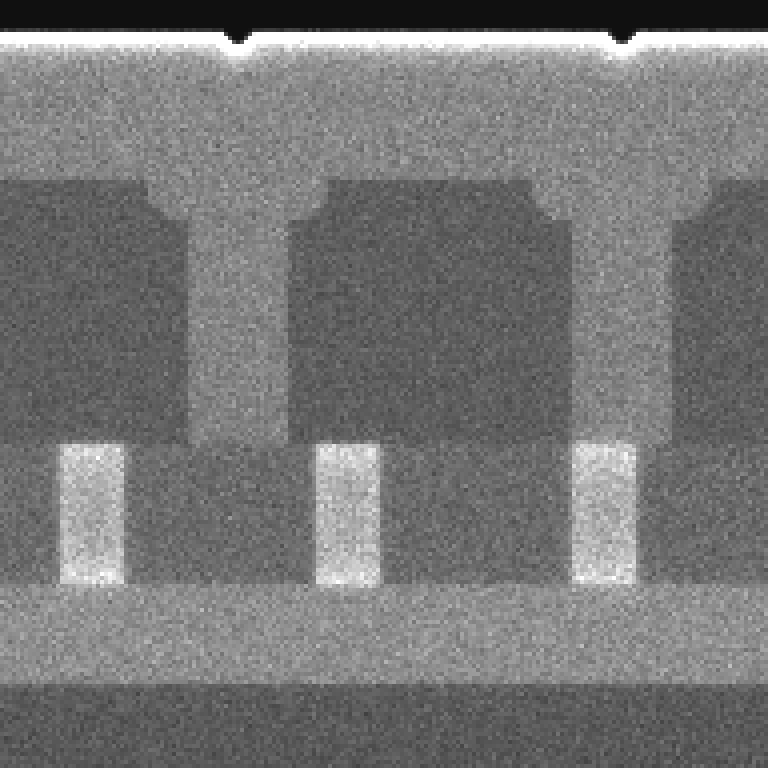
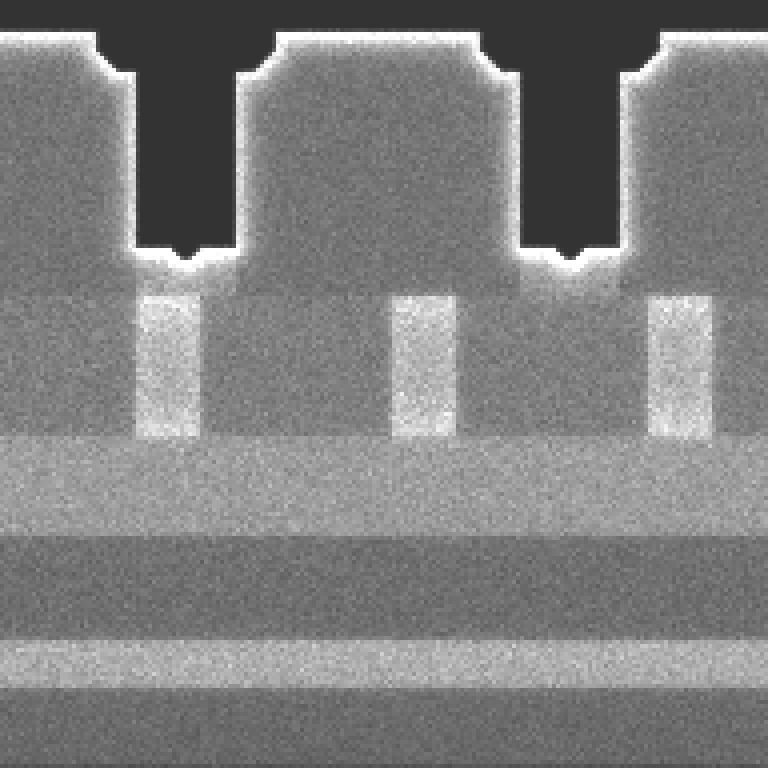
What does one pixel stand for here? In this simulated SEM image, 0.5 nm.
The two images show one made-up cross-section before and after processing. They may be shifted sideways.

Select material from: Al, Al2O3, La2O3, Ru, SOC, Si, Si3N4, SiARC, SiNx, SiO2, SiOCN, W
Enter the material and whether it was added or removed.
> SiO2 / removed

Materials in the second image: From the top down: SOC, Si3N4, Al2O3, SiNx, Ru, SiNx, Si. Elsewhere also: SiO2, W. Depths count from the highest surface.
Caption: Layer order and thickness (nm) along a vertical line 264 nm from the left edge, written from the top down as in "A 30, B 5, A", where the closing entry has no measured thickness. empty 108, SiO2 24, Si3N4 70, Al2O3 50, SiNx 52, Ru 24, SiNx 38, Si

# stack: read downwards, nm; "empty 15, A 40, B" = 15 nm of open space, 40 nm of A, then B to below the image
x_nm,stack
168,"SOC 132, Si3N4 70, Al2O3 50, SiNx 52, Ru 24, SiNx 38, Si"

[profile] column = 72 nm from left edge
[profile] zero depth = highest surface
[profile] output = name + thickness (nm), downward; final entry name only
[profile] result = empty 108, SiO2 24, W 70, Al2O3 50, SiNx 52, Ru 24, SiNx 38, Si